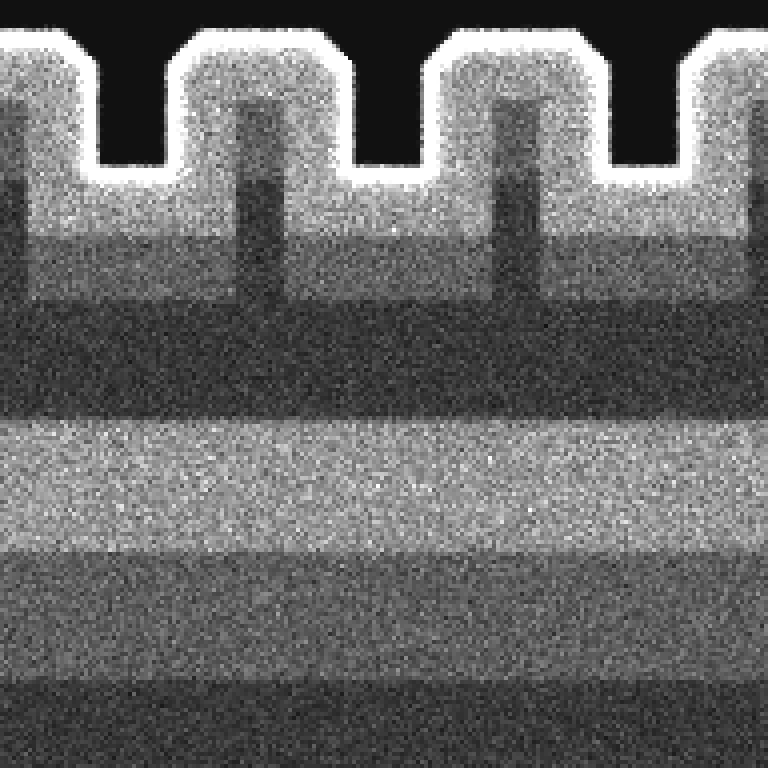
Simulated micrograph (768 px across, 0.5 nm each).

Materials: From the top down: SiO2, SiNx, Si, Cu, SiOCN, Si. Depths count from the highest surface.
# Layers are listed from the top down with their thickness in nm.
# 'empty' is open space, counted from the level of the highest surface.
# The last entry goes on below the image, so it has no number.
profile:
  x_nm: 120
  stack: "SiO2 34, SiOCN 40, Si 120, Cu 66, SiOCN 64, Si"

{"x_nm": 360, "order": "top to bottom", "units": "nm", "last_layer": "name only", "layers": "SiO2 102, SiNx 32, Si 60, Cu 66, SiOCN 64, Si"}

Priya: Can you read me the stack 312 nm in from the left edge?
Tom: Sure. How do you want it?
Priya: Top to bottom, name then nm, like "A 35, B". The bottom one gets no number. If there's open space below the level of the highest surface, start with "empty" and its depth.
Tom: empty 68, SiO2 34, SiNx 32, Si 60, Cu 66, SiOCN 64, Si